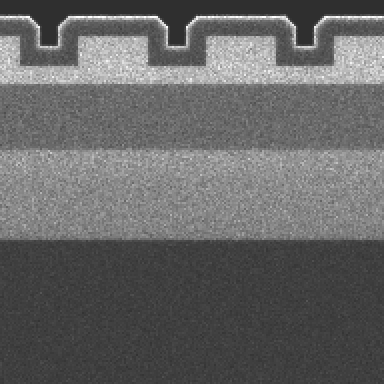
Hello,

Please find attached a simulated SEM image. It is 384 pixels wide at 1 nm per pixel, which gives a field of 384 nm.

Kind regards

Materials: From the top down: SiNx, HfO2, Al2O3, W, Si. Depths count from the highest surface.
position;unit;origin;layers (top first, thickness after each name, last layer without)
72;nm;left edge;SiNx 50, HfO2 18, Al2O3 66, W 90, Si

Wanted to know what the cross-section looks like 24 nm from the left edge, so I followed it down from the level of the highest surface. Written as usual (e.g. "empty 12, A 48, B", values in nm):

SiNx 50, HfO2 18, Al2O3 66, W 90, Si